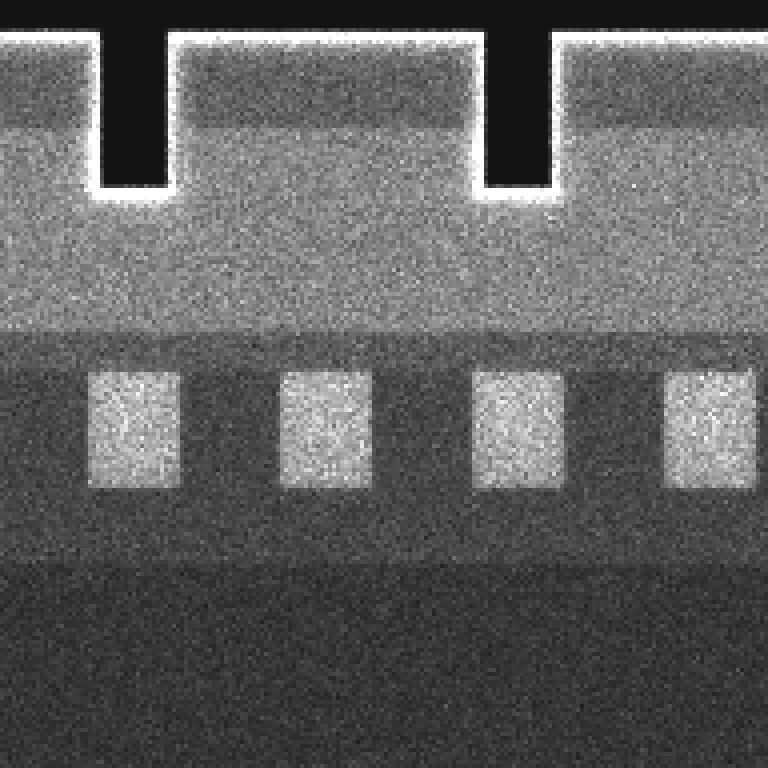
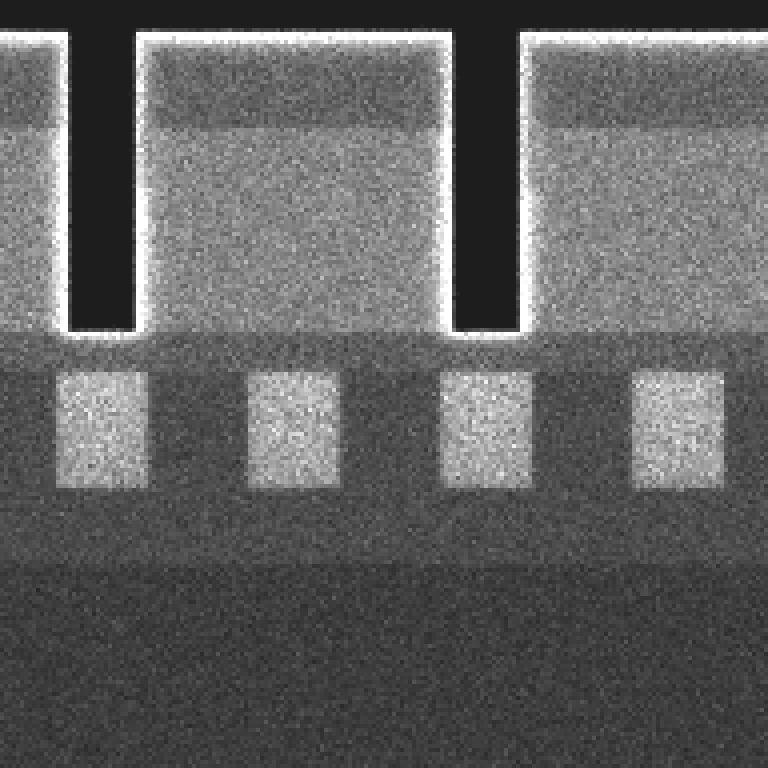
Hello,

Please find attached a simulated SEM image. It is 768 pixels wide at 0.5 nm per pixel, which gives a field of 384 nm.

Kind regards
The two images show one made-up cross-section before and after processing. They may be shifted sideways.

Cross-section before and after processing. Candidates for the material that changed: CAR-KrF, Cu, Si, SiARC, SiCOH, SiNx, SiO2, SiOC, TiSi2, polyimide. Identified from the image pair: SiO2 (removed).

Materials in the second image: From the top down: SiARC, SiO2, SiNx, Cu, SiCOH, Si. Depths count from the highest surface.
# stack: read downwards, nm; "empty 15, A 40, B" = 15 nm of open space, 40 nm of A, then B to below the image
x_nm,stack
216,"SiARC 48, SiO2 102, SiNx 20, SiCOH 96, Si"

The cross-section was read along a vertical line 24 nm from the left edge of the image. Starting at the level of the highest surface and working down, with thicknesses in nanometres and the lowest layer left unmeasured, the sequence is SiARC 48, SiO2 102, SiNx 20, SiCOH 96, Si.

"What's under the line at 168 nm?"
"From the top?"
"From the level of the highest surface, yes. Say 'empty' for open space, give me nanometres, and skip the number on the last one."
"SiARC 48, SiO2 102, SiNx 20, Cu 58, SiCOH 38, Si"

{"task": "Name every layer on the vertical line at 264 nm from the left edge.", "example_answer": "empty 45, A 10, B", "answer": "SiARC 78, SiO2 72, SiNx 20, Cu 58, SiCOH 38, Si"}